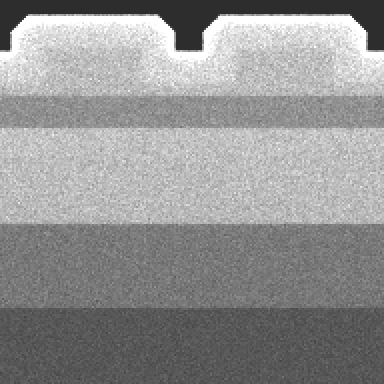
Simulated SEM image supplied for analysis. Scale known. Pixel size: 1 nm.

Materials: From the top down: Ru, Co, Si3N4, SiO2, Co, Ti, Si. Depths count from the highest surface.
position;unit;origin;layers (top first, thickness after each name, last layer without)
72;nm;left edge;Ru 32, Co 48, Si3N4 32, SiO2 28, Co 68, Ti 84, Si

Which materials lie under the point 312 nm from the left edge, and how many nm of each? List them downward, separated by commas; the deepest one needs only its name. Ru 32, Co 48, Si3N4 32, SiO2 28, Co 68, Ti 84, Si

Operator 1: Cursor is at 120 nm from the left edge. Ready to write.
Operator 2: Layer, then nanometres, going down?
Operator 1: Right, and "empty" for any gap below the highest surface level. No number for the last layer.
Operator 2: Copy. Ru 32, Co 48, Si3N4 32, SiO2 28, Co 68, Ti 84, Si